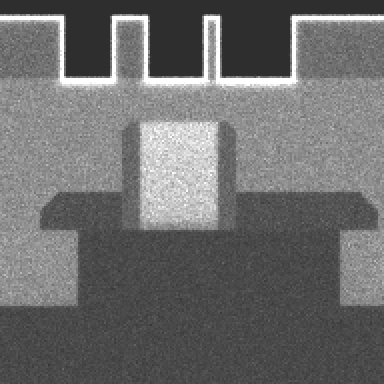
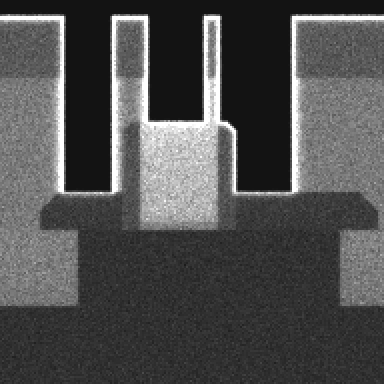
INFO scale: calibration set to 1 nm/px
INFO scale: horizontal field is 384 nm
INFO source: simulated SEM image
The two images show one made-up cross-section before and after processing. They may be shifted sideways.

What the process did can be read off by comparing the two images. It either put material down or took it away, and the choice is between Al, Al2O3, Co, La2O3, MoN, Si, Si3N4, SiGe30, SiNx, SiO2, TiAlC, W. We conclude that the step removed SiO2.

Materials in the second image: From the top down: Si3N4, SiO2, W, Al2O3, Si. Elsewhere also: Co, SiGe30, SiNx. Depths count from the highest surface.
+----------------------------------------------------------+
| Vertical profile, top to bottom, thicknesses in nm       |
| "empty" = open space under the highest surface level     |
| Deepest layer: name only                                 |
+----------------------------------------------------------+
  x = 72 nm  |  empty 176, SiGe30 38, Co 76, Si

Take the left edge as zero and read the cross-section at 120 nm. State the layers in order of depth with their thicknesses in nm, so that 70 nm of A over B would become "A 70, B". Si3N4 62, SiO2 114, SiGe30 38, Si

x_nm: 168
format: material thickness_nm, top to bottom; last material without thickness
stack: empty 106, W 100, Al2O3 8, Si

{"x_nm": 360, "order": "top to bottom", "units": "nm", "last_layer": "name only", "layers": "Si3N4 62, SiO2 116, SiGe30 36, Co 76, Si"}